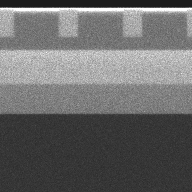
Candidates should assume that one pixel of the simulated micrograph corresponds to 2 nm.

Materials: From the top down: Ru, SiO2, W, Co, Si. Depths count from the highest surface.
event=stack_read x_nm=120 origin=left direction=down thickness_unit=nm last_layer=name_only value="Ru 58, SiO2 26, W 68, Co 60, Si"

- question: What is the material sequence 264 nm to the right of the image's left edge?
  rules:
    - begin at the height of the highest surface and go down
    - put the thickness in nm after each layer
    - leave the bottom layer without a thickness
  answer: Ru 58, SiO2 26, W 68, Co 60, Si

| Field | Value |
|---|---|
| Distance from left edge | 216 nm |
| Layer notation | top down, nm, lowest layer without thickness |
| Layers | SiO2 84, W 68, Co 60, Si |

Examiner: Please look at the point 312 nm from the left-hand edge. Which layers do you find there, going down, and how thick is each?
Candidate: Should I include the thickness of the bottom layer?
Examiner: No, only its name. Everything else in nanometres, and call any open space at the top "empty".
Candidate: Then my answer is SiO2 84, W 68, Co 60, Si